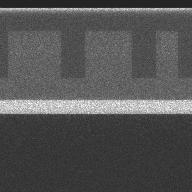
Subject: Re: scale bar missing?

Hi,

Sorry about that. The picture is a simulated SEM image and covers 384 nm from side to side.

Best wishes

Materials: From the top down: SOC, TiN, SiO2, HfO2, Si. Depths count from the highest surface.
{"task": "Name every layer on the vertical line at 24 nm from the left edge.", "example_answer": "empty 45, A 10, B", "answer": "SOC 46, TiN 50, SiO2 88, HfO2 28, Si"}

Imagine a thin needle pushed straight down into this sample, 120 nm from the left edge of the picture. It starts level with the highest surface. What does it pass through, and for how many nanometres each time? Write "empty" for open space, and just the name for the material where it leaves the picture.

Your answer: SOC 46, TiN 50, SiO2 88, HfO2 28, Si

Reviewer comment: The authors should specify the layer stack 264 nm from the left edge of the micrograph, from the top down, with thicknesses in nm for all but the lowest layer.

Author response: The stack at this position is SOC 140, SiO2 44, HfO2 28, Si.